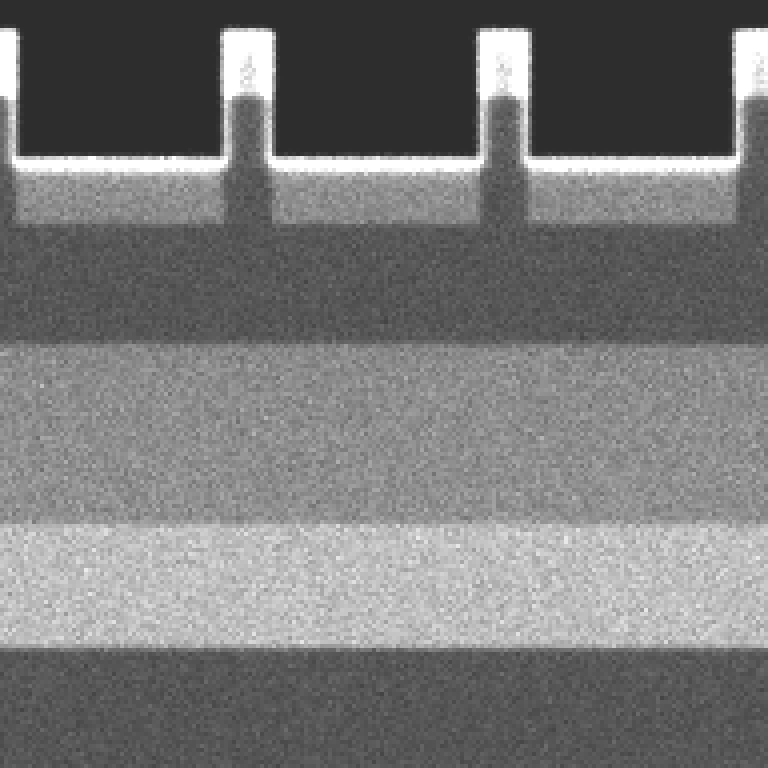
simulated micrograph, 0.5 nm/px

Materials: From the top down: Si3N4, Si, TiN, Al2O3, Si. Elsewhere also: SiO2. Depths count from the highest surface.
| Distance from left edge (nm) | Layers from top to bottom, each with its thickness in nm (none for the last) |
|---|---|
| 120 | SiO2 32, Si 124, TiN 90, Al2O3 62, Si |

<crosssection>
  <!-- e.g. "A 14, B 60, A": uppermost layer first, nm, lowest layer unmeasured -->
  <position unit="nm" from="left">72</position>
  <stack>empty 64, Si3N4 32, Si 60, TiN 90, Al2O3 62, Si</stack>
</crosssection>